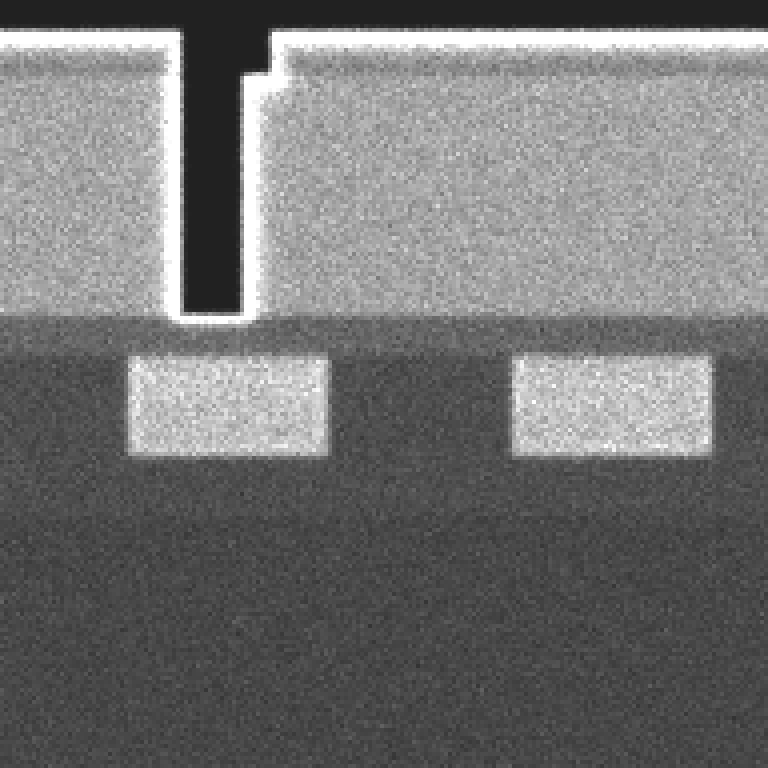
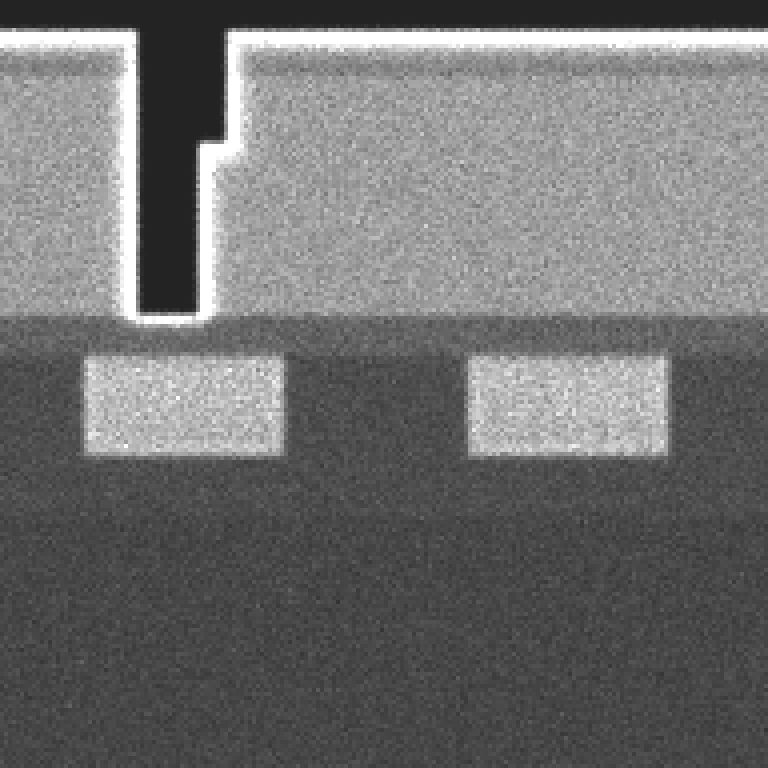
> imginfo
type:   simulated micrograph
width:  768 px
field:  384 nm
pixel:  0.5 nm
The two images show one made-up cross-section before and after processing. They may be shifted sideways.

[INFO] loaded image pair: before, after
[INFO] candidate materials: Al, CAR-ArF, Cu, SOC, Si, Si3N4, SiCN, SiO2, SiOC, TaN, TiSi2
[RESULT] removed SiO2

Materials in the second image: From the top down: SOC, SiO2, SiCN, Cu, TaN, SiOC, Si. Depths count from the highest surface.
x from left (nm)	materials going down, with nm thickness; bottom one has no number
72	empty 142, SiCN 20, Cu 44, TaN 6, SiOC 30, Si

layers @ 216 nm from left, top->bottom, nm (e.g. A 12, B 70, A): SOC 22, SiO2 120, SiCN 20, SiOC 80, Si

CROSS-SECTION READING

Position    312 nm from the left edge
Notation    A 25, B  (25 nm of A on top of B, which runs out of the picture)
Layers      SOC 22, SiO2 120, SiCN 20, Cu 44, TaN 6, SiOC 30, Si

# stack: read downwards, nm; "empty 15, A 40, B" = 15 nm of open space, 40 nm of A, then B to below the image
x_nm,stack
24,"SOC 22, SiO2 120, SiCN 20, SiOC 80, Si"